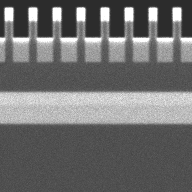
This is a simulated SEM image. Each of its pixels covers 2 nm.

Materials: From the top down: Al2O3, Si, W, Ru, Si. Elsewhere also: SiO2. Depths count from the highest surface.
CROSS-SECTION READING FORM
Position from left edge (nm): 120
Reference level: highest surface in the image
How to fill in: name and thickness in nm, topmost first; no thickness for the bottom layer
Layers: Al2O3 26, Si 142, W 26, Ru 38, Si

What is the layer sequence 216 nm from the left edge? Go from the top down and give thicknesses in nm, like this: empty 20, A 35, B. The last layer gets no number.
Al2O3 26, Si 142, W 26, Ru 38, Si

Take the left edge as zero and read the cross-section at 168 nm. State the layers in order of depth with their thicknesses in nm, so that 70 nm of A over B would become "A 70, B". Al2O3 26, Si 142, W 26, Ru 38, Si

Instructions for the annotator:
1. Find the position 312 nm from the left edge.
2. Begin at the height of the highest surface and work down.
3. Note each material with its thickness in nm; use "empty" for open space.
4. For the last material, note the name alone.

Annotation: Al2O3 26, Si 142, W 26, Ru 38, Si